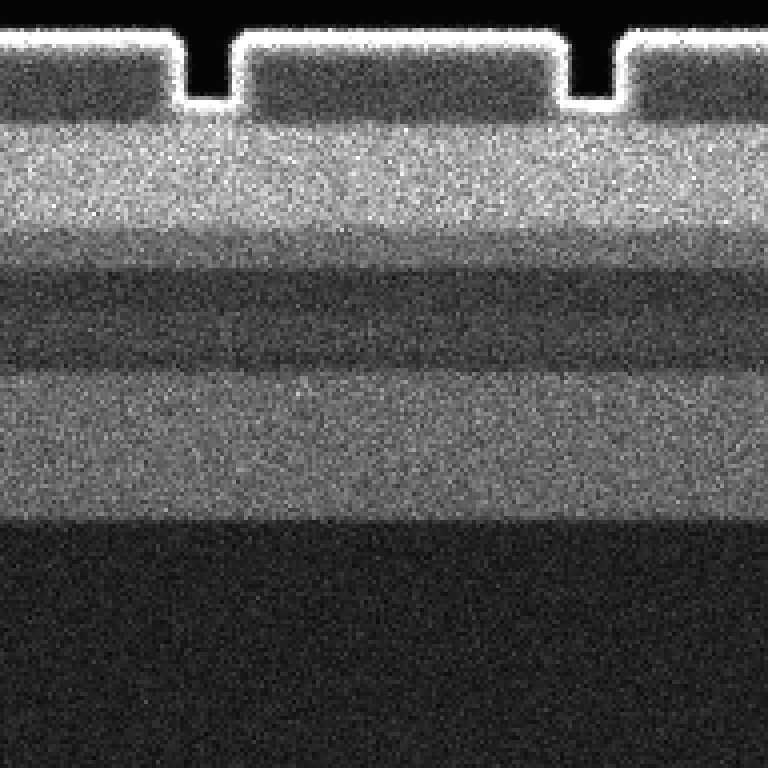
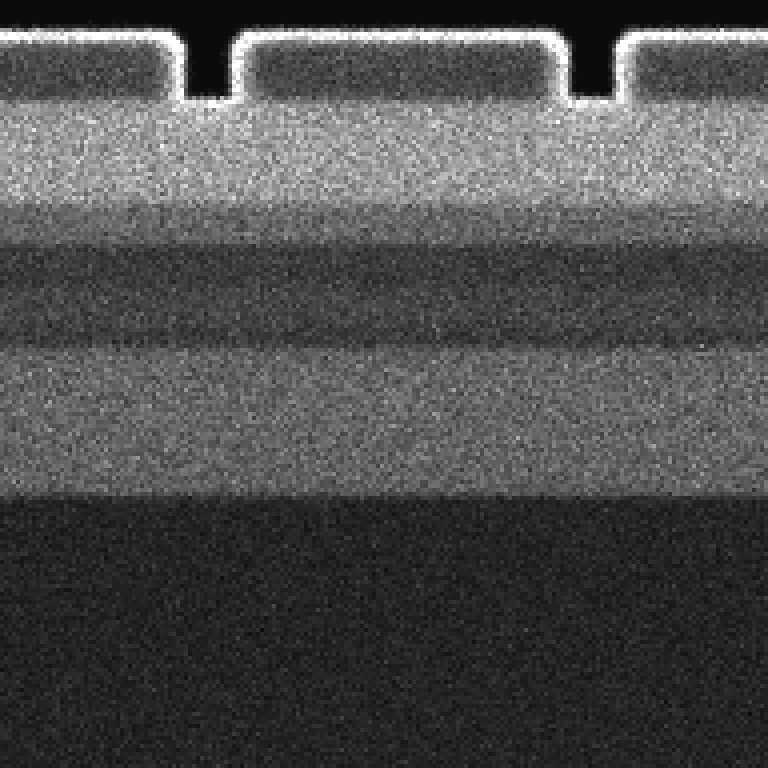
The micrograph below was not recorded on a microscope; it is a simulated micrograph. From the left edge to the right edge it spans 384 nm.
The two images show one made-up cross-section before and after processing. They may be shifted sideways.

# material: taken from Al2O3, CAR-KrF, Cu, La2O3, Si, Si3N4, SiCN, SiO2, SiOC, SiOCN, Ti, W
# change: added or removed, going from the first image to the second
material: SiO2
change: removed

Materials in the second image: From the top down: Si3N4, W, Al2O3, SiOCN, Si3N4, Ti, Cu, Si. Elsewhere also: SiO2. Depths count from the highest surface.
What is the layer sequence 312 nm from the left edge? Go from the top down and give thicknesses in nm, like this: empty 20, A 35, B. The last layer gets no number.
empty 2, SiO2 32, W 52, Al2O3 20, SiOCN 22, Si3N4 20, Ti 10, Cu 74, Si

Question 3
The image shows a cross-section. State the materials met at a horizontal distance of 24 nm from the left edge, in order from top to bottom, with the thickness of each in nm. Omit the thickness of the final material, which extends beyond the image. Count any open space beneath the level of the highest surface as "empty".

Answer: Si3N4 34, W 52, Al2O3 20, SiOCN 22, Si3N4 20, Ti 10, Cu 74, Si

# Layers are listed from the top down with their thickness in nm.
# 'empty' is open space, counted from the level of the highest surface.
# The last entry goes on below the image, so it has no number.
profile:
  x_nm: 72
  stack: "Si3N4 34, W 52, Al2O3 20, SiOCN 22, Si3N4 20, Ti 10, Cu 74, Si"